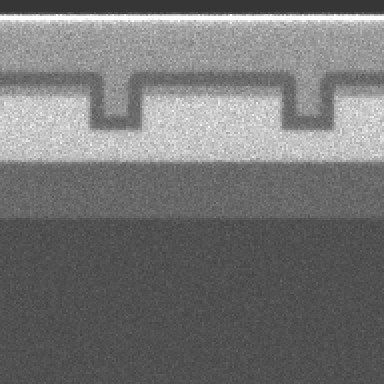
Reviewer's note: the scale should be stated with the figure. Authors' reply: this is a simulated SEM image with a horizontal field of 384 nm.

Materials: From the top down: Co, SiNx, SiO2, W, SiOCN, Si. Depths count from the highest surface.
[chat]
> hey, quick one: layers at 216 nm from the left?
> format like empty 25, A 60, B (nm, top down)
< Co 56, SiNx 14, SiO2 10, W 66, SiOCN 56, Si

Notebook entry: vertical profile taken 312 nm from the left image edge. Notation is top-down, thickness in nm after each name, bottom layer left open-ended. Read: Co 100, SiNx 14, W 32, SiOCN 56, Si